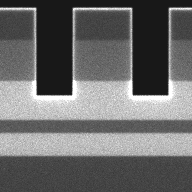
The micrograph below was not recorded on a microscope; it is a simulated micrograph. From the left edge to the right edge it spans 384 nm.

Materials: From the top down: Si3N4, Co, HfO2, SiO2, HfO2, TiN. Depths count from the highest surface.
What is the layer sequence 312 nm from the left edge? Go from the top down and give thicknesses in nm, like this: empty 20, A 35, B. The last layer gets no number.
empty 176, HfO2 48, SiO2 26, HfO2 46, TiN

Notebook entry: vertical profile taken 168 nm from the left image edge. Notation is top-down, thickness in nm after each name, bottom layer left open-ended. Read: Si3N4 64, Co 82, HfO2 78, SiO2 26, HfO2 46, TiN